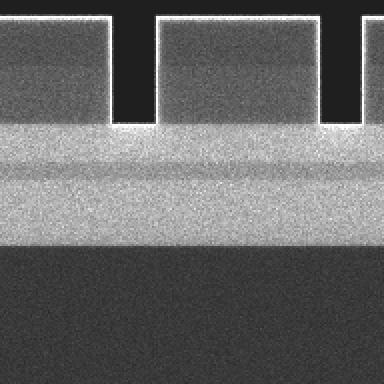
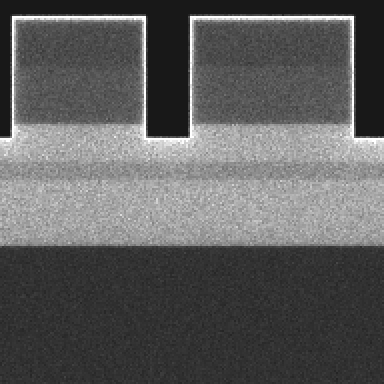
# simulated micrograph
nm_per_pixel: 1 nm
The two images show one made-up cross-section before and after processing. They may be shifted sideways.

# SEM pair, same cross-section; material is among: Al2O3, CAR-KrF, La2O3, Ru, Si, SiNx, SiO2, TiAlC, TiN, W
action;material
removed;W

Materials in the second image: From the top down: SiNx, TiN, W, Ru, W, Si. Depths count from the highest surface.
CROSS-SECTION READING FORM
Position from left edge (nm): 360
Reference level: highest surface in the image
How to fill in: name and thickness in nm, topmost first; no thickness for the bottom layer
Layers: empty 122, W 24, Ru 18, W 66, Si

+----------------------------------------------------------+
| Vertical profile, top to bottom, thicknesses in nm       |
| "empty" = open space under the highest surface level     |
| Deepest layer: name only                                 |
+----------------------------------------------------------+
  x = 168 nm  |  empty 122, W 24, Ru 18, W 66, Si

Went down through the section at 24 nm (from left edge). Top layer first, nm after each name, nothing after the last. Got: SiNx 50, TiN 58, W 38, Ru 18, W 66, Si